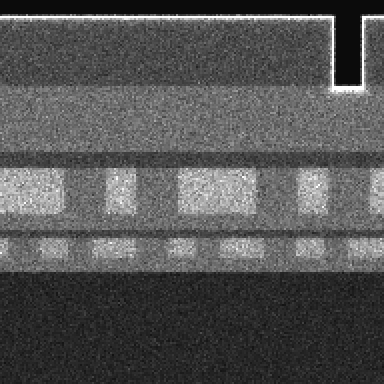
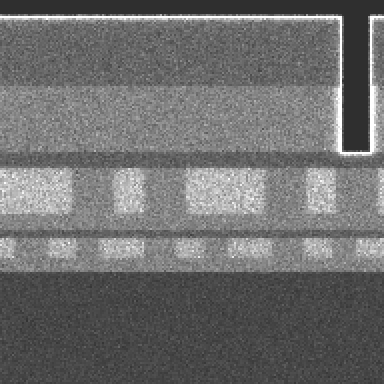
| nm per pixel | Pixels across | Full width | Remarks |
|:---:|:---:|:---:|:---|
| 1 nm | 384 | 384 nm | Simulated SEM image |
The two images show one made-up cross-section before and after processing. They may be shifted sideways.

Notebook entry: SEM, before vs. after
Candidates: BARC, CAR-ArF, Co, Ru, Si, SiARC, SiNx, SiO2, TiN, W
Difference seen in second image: SiO2 removed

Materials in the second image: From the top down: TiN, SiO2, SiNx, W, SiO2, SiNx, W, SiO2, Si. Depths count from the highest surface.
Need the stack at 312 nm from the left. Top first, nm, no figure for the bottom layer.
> TiN 70, SiO2 66, SiNx 16, W 46, SiO2 16, SiNx 8, W 20, SiO2 14, Si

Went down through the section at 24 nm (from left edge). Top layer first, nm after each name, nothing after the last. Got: TiN 70, SiO2 66, SiNx 16, W 46, SiO2 16, SiNx 8, SiO2 34, Si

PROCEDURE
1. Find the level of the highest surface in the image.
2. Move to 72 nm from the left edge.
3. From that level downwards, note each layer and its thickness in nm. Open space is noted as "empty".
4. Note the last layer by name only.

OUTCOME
TiN 70, SiO2 66, SiNx 16, SiO2 62, SiNx 8, W 20, SiO2 14, Si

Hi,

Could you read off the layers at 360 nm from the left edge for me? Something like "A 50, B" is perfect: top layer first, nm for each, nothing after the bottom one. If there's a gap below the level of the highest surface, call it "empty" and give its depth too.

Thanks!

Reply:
empty 136, SiNx 16, SiO2 62, SiNx 8, W 20, SiO2 14, Si